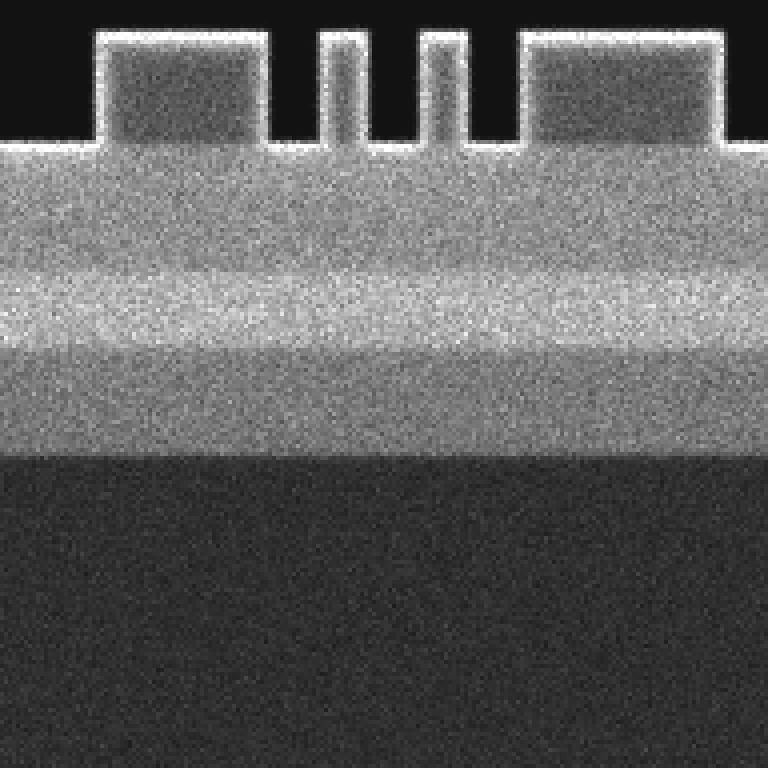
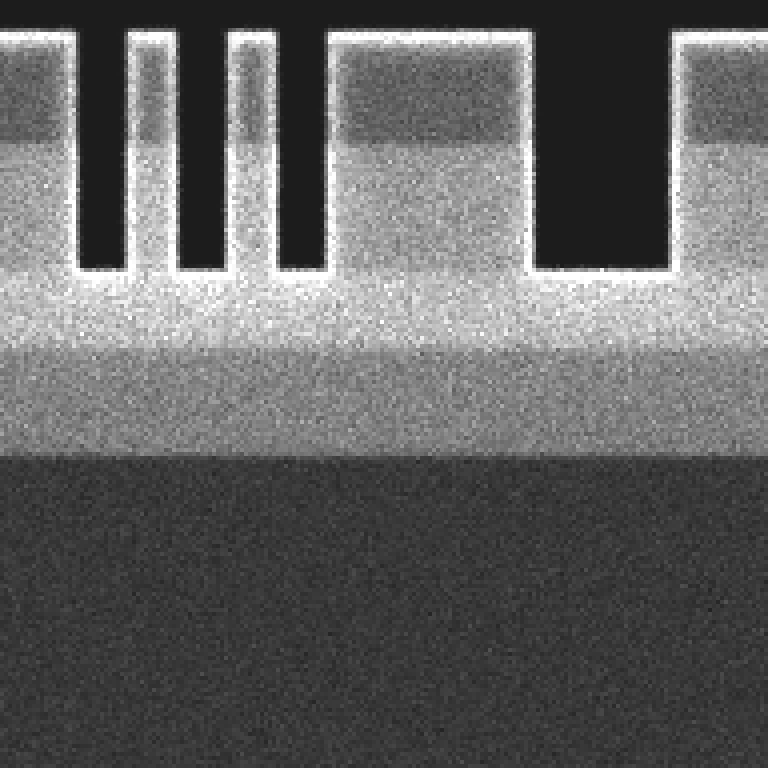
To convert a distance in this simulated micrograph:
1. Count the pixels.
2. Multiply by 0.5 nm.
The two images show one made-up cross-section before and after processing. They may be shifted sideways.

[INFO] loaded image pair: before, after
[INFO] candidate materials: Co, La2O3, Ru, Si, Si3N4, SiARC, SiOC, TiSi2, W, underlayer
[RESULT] removed Ru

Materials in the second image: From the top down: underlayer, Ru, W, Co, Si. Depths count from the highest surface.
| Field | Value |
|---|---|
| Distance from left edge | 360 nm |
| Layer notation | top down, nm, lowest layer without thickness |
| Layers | underlayer 56, Ru 64, W 38, Co 54, Si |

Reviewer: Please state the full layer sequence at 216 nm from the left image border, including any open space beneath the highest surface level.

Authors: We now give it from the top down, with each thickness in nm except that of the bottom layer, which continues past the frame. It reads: underlayer 56, Ru 64, W 38, Co 54, Si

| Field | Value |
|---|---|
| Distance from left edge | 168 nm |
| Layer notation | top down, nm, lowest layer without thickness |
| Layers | underlayer 56, Ru 64, W 38, Co 54, Si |